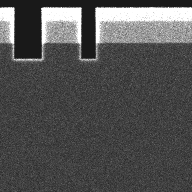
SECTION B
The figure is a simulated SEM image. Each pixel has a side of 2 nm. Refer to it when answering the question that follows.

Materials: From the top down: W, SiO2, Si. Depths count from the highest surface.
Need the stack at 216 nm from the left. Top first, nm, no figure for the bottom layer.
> W 26, SiO2 44, Si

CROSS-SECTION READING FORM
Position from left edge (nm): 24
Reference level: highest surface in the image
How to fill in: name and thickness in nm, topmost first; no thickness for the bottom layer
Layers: W 26, SiO2 44, Si